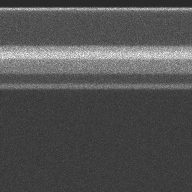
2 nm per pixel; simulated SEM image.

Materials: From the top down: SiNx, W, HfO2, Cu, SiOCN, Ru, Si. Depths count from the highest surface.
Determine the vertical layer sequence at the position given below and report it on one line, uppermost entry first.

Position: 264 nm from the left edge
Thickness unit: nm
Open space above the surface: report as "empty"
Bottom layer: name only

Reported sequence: SiNx 76, W 12, HfO2 14, Cu 30, SiOCN 20, Ru 10, Si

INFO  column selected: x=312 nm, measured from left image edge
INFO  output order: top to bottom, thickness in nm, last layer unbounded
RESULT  SiNx 76, W 12, HfO2 14, Cu 30, SiOCN 20, Ru 10, Si